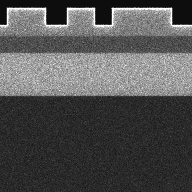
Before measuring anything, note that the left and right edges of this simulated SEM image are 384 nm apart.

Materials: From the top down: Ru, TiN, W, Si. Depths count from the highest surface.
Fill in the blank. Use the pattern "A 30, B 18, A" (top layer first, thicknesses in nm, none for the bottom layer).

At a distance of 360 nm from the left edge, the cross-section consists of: empty 34, Ru 22, TiN 34, W 86, Si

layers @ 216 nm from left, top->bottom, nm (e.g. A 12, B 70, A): empty 34, Ru 22, TiN 34, W 86, Si